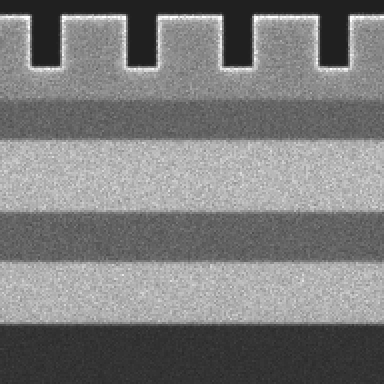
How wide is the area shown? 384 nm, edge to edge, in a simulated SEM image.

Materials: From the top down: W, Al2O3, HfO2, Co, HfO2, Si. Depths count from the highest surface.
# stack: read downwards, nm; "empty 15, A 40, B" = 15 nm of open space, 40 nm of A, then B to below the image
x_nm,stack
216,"W 84, Al2O3 40, HfO2 72, Co 50, HfO2 62, Si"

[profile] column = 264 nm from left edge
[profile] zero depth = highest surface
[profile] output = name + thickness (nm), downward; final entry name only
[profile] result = W 84, Al2O3 40, HfO2 72, Co 50, HfO2 62, Si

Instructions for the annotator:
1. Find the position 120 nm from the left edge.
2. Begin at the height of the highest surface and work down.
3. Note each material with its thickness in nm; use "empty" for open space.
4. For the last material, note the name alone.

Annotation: W 84, Al2O3 40, HfO2 72, Co 50, HfO2 62, Si